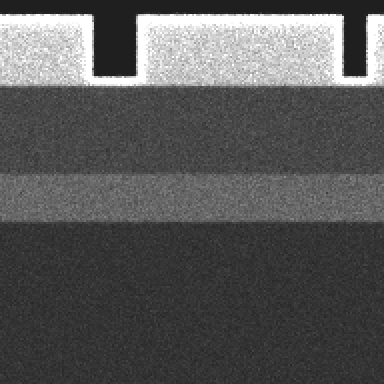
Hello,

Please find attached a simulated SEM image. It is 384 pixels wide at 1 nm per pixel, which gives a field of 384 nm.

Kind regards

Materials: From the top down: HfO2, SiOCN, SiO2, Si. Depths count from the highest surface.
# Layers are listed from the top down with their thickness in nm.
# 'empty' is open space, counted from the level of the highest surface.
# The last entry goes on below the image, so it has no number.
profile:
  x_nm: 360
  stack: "empty 62, HfO2 8, SiOCN 88, SiO2 48, Si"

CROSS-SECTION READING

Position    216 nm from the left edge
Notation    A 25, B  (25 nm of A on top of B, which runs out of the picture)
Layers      HfO2 70, SiOCN 88, SiO2 48, Si